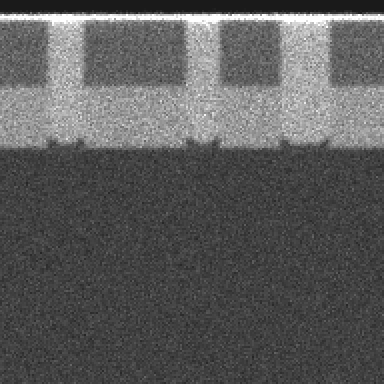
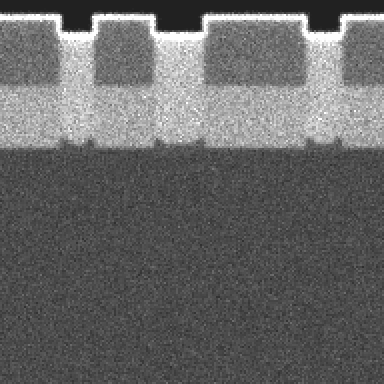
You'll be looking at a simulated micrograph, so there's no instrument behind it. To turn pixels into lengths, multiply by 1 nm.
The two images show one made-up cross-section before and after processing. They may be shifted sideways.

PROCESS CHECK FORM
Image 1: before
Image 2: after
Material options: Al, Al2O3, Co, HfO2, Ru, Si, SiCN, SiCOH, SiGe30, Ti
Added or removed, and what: removed, Ru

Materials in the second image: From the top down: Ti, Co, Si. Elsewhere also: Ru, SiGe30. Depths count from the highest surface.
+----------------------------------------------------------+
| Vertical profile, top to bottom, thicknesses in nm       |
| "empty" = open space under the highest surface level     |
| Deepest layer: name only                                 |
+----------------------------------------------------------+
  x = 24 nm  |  Ti 70, Co 62, Si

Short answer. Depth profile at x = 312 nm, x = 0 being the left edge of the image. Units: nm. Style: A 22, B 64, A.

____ empty 18, Ru 106, SiGe30 14, Si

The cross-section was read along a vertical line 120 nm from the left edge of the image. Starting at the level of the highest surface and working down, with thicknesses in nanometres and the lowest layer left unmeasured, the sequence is Ti 70, Co 62, Si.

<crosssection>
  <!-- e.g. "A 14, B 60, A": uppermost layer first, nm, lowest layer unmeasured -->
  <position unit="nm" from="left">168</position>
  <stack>empty 18, Ru 110, SiGe30 10, Si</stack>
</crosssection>